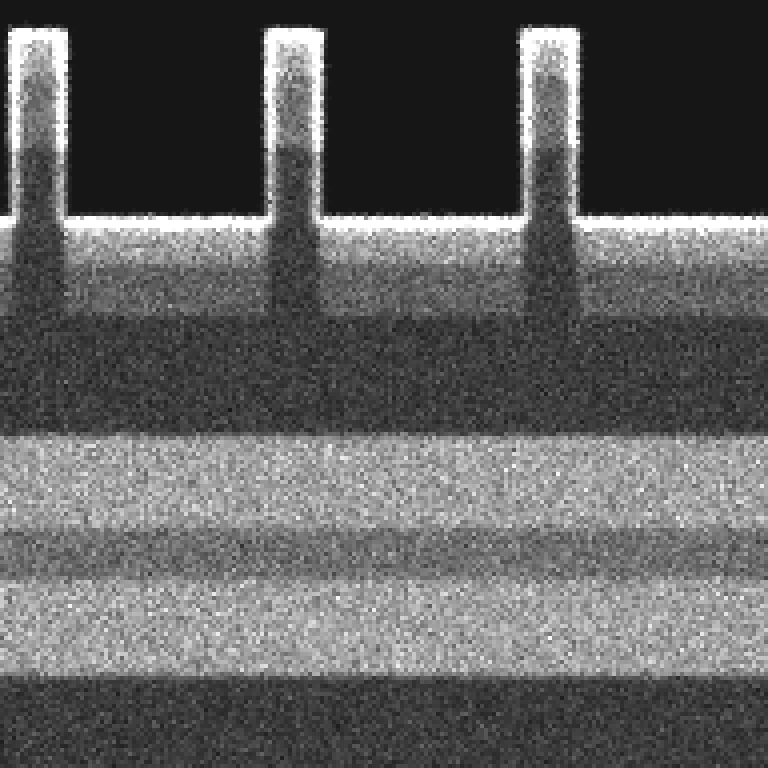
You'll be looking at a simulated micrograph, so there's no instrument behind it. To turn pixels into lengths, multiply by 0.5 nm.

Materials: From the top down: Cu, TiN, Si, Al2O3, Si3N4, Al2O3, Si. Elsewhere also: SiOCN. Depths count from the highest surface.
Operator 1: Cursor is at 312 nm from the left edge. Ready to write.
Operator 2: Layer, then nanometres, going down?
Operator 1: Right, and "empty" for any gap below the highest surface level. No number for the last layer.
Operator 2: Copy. empty 94, Cu 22, SiOCN 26, Si 60, Al2O3 46, Si3N4 26, Al2O3 48, Si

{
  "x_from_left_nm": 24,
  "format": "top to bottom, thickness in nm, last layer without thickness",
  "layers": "Cu 22, TiN 36, Si 144, Al2O3 46, Si3N4 26, Al2O3 48, Si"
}